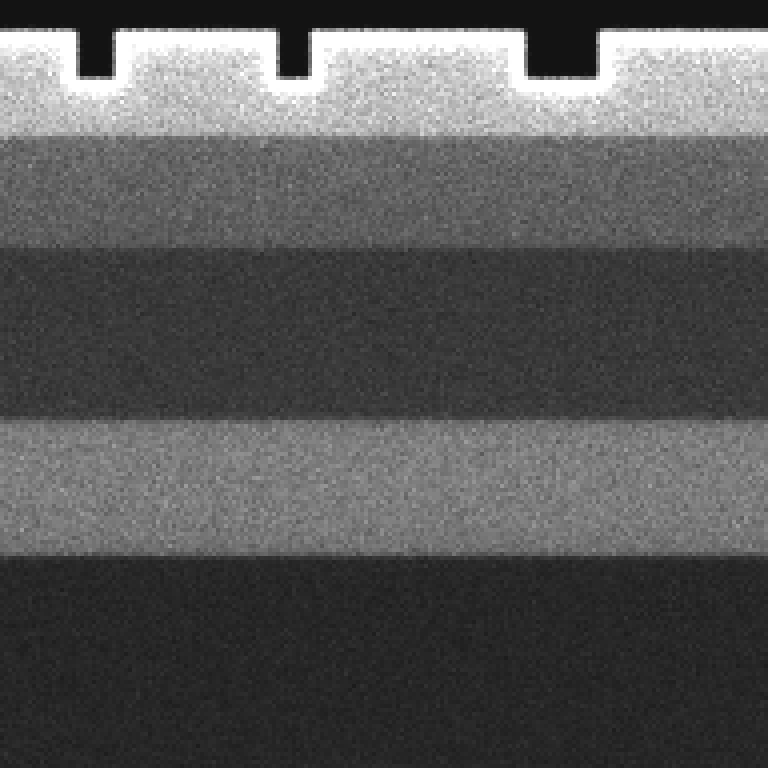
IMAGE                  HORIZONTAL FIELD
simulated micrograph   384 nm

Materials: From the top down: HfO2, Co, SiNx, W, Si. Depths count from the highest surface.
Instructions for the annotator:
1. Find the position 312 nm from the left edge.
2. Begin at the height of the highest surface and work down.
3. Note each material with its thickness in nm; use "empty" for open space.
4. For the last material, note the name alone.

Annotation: HfO2 52, Co 56, SiNx 86, W 68, Si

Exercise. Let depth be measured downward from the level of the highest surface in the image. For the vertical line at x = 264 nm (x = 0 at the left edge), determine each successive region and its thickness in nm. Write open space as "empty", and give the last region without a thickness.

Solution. empty 24, HfO2 28, Co 56, SiNx 86, W 68, Si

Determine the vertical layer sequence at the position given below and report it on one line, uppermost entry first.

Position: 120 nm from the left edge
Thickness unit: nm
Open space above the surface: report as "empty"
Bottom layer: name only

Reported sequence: HfO2 52, Co 56, SiNx 86, W 68, Si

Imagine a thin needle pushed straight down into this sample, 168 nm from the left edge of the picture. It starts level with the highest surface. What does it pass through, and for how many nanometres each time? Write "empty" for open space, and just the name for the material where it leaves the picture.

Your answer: HfO2 52, Co 56, SiNx 86, W 68, Si